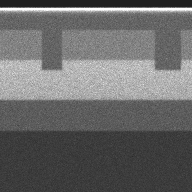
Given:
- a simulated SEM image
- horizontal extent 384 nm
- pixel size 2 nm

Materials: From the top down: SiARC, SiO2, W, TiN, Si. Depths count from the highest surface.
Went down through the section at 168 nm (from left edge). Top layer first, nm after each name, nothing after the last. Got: SiARC 44, SiO2 60, W 80, TiN 62, Si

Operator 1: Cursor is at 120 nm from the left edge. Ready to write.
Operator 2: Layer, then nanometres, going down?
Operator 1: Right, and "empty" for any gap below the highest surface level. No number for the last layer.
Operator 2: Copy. SiARC 124, W 60, TiN 62, Si